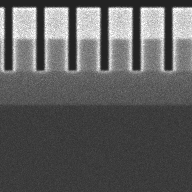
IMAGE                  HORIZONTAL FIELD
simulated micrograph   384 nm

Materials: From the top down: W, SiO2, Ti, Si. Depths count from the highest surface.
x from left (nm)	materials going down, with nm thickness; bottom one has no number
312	W 62, SiO2 64, Ti 68, Si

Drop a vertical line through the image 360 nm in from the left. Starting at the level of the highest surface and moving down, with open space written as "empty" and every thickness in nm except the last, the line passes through W 62, SiO2 64, Ti 68, Si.